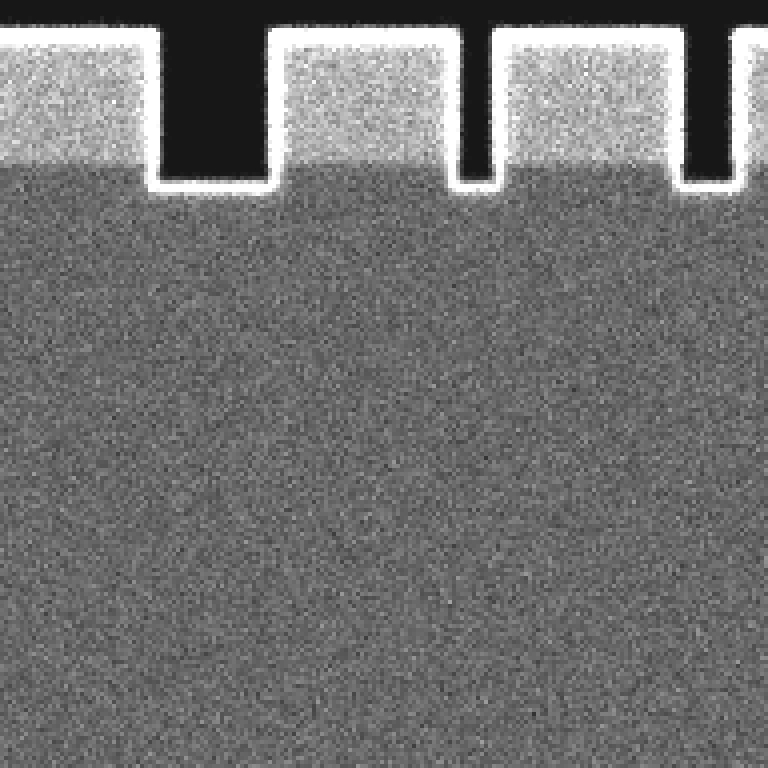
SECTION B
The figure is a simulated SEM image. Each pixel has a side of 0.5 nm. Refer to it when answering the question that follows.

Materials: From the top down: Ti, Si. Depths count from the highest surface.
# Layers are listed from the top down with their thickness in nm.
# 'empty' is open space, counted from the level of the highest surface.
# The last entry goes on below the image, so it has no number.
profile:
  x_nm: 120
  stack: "empty 76, Si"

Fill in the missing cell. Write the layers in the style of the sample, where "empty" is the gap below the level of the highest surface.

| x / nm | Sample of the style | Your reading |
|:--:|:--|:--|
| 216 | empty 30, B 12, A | Ti 66, Si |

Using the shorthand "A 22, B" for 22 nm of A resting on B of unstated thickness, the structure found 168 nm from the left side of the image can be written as Ti 66, Si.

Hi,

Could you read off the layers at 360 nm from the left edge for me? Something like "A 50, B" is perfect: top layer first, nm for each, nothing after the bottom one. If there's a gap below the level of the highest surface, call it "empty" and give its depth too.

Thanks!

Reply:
empty 76, Si